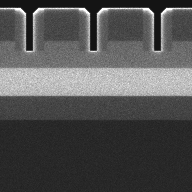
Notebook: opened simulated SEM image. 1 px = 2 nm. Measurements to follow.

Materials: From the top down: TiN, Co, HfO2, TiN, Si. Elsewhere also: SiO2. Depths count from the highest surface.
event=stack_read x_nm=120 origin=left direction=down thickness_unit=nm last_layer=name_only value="TiN 66, Co 54, HfO2 56, TiN 48, Si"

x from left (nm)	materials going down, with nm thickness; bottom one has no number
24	TiN 66, Co 54, HfO2 56, TiN 48, Si